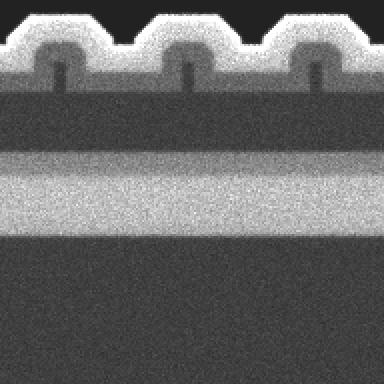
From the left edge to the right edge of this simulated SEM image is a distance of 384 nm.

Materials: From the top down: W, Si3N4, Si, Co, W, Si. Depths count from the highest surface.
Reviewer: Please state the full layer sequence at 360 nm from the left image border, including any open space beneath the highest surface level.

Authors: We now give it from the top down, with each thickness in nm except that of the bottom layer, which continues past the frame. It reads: empty 16, W 40, Si3N4 20, Si 60, Co 24, W 60, Si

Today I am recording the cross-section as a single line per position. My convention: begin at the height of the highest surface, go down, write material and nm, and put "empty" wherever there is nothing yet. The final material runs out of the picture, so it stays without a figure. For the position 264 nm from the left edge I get empty 22, W 34, Si3N4 20, Si 60, Co 24, W 60, Si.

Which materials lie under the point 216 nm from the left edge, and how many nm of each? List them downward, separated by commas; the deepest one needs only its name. W 56, Si3N4 20, Si 60, Co 24, W 60, Si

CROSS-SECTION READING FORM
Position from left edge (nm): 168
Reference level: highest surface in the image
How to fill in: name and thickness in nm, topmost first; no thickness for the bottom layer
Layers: W 30, Si3N4 46, Si 60, Co 24, W 60, Si